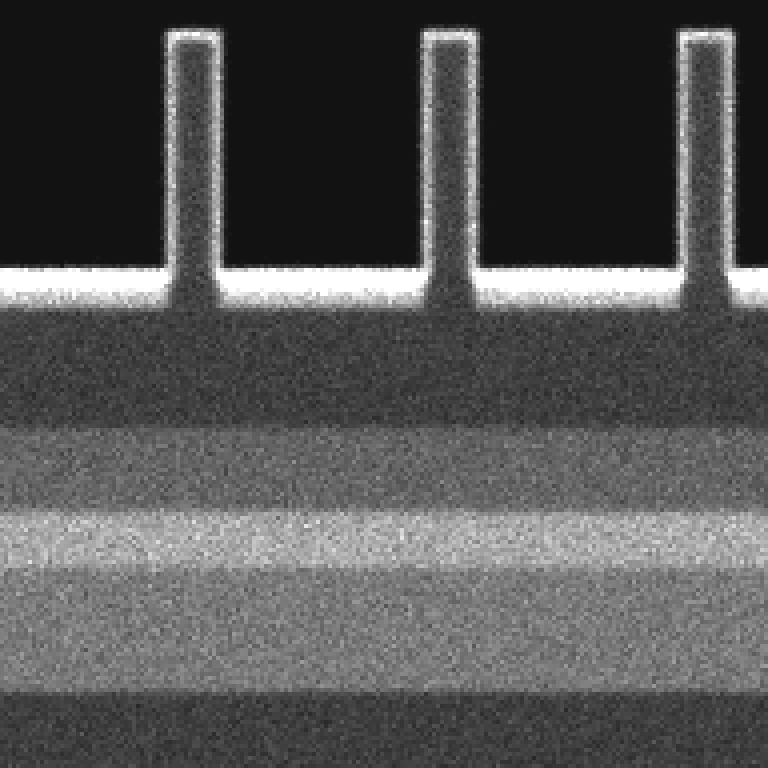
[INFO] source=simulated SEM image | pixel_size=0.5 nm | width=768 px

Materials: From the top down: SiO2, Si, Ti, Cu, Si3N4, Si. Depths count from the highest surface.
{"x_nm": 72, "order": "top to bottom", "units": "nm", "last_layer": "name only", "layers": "empty 120, SiO2 18, Si 60, Ti 42, Cu 28, Si3N4 62, Si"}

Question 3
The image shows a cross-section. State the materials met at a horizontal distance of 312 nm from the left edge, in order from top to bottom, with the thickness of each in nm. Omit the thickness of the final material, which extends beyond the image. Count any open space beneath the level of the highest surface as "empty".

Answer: empty 120, SiO2 18, Si 60, Ti 42, Cu 28, Si3N4 62, Si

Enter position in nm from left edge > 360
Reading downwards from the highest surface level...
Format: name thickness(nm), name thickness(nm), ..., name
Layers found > Si 198, Ti 42, Cu 28, Si3N4 62, Si